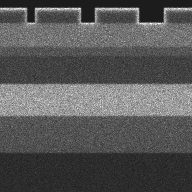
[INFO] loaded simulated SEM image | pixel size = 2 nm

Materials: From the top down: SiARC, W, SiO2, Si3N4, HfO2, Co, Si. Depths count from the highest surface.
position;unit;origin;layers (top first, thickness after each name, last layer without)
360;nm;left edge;SiARC 30, W 48, SiO2 18, Si3N4 56, HfO2 64, Co 74, Si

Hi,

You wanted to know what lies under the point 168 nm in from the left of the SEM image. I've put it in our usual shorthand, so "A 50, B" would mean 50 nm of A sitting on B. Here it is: empty 30, W 48, SiO2 18, Si3N4 56, HfO2 64, Co 74, Si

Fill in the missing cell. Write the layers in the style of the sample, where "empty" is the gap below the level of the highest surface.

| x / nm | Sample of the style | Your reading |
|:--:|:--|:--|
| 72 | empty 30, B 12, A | SiARC 30, W 48, SiO2 18, Si3N4 56, HfO2 64, Co 74, Si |